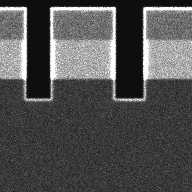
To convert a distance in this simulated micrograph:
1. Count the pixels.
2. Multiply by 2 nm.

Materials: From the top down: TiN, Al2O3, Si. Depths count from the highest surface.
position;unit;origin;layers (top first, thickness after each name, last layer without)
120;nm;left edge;TiN 64, Al2O3 78, Si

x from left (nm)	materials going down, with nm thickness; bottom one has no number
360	TiN 64, Al2O3 78, Si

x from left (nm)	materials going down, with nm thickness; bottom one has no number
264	empty 182, Si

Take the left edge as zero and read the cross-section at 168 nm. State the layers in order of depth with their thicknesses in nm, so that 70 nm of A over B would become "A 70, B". TiN 64, Al2O3 78, Si